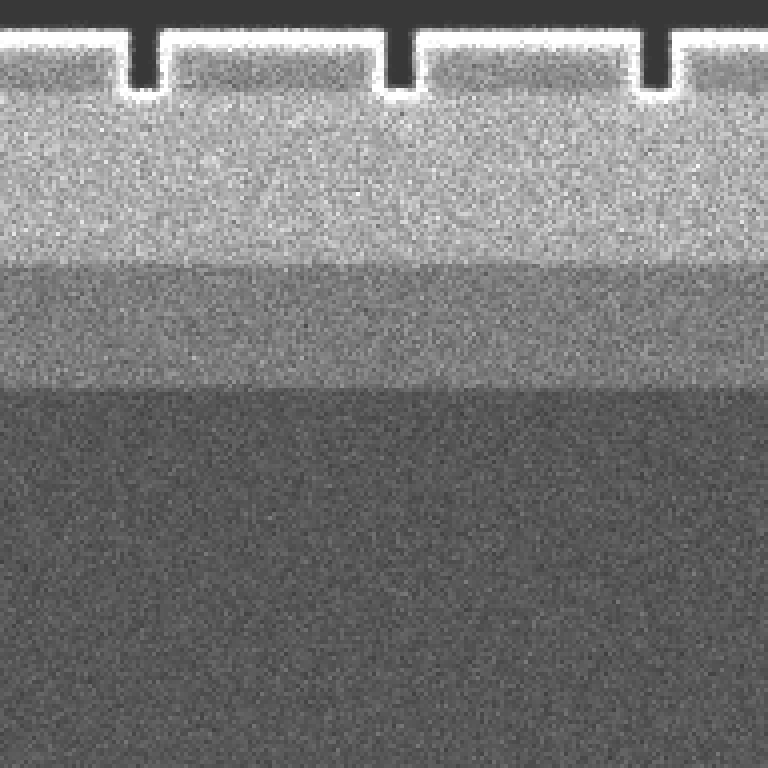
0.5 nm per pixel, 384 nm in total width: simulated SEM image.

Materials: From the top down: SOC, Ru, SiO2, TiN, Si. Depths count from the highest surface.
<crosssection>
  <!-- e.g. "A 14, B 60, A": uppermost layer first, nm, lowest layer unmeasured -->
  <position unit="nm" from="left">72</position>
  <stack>empty 30, Ru 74, SiO2 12, TiN 62, Si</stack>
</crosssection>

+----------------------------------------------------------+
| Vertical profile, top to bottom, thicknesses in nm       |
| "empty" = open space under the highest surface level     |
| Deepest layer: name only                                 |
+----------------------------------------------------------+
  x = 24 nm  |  SOC 30, Ru 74, SiO2 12, TiN 62, Si